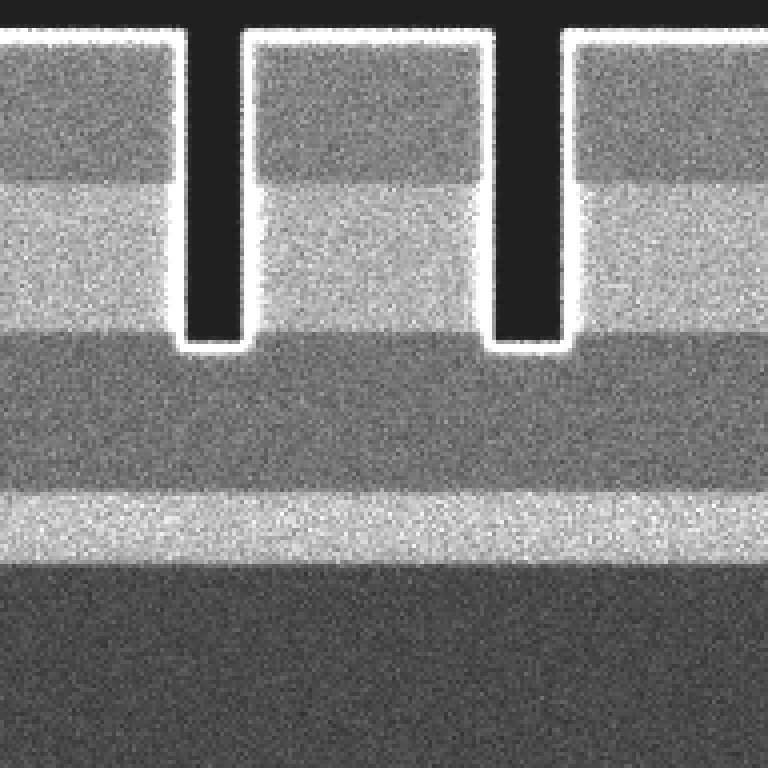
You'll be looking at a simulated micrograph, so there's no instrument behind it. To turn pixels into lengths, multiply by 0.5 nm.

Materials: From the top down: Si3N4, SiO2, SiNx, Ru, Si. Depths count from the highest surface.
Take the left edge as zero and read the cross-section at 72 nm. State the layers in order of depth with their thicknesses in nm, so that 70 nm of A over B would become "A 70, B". Si3N4 76, SiO2 74, SiNx 80, Ru 36, Si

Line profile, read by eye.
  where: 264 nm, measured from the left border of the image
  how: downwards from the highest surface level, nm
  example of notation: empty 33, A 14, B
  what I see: empty 156, SiNx 74, Ru 36, Si